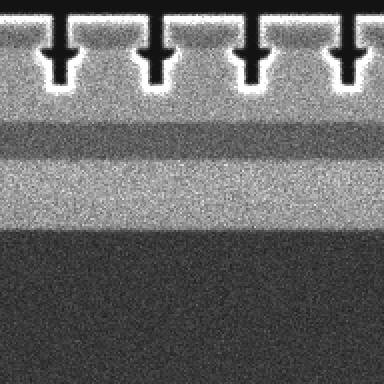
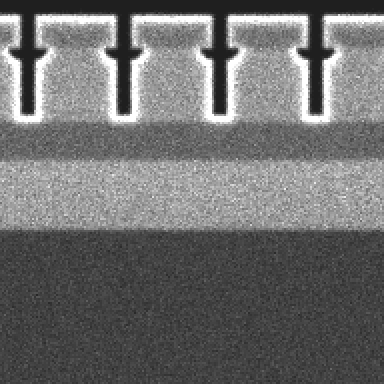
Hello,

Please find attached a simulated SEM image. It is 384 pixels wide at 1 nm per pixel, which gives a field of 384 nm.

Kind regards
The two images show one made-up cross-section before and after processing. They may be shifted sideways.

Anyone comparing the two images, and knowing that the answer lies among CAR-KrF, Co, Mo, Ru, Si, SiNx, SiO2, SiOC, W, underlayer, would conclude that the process removed SiO2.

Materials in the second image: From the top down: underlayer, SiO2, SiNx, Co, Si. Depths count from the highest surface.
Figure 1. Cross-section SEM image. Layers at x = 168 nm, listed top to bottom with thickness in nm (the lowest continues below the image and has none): underlayer 32, SiO2 74, SiNx 38, Co 70, Si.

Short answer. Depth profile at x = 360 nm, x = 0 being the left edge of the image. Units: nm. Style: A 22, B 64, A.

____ underlayer 32, SiO2 74, SiNx 38, Co 70, Si